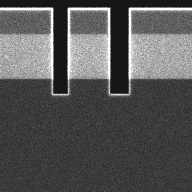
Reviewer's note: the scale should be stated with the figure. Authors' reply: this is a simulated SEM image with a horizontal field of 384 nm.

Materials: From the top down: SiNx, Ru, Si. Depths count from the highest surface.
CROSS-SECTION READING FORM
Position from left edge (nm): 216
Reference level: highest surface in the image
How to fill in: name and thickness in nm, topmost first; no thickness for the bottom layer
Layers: SiNx 52, Ru 90, Si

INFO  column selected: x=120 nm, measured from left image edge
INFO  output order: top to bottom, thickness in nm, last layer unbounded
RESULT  empty 172, Si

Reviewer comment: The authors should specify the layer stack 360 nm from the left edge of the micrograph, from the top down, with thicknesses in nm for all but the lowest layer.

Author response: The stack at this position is SiNx 52, Ru 90, Si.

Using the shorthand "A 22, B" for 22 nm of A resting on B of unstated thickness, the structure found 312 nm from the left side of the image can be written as SiNx 52, Ru 90, Si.